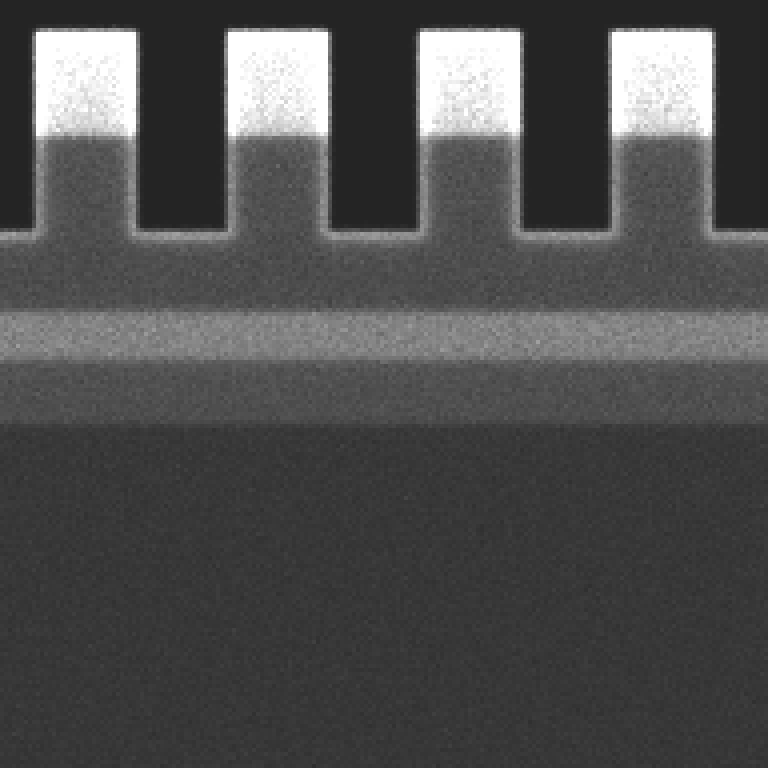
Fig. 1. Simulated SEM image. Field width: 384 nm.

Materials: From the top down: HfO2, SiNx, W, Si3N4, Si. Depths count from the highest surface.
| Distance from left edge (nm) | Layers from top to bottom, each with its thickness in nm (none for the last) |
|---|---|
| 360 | empty 100, SiNx 40, W 24, Si3N4 32, Si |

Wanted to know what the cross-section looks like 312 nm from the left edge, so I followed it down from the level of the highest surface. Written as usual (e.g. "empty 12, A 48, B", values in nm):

HfO2 52, SiNx 88, W 24, Si3N4 32, Si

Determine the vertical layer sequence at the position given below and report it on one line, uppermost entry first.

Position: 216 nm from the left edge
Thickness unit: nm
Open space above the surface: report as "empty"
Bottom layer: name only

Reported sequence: HfO2 52, SiNx 88, W 24, Si3N4 32, Si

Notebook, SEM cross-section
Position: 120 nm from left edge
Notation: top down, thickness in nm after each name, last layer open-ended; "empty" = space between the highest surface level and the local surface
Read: HfO2 52, SiNx 88, W 24, Si3N4 32, Si